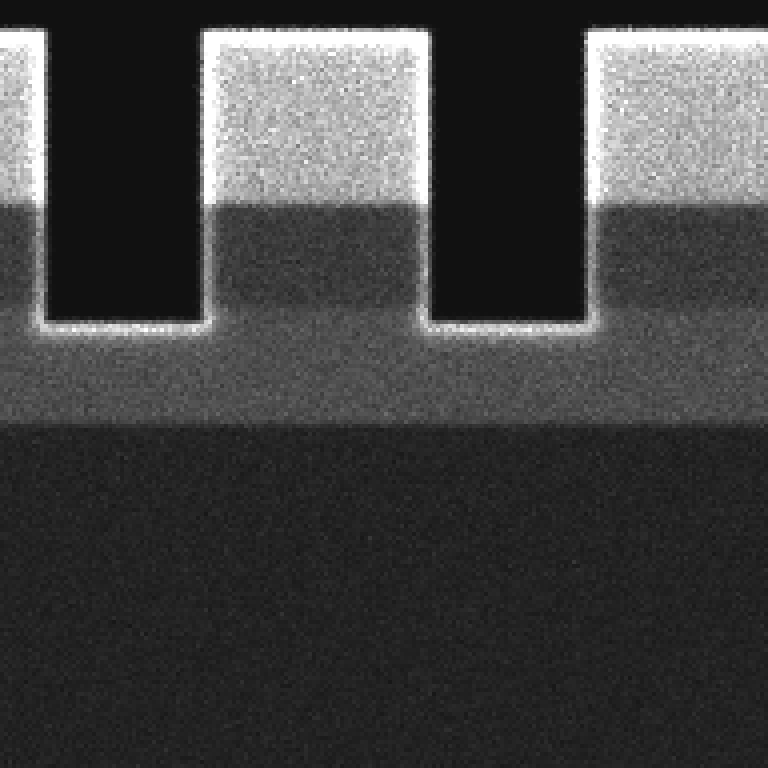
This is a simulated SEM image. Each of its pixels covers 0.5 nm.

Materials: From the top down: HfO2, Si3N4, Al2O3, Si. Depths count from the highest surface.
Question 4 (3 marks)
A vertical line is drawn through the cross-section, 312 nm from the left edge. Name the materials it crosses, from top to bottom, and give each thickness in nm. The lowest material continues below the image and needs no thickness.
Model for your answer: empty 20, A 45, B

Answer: HfO2 86, Si3N4 52, Al2O3 58, Si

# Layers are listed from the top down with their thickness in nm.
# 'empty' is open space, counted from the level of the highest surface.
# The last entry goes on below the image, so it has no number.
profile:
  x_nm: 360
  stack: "HfO2 86, Si3N4 52, Al2O3 58, Si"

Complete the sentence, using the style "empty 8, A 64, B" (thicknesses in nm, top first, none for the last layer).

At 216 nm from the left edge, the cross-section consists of empty 146, Al2O3 50, Si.